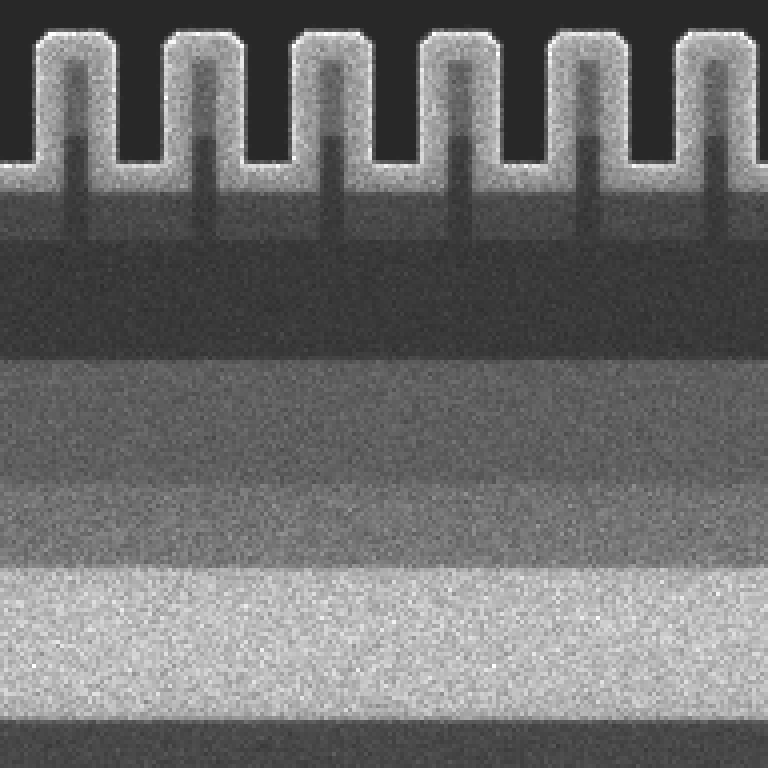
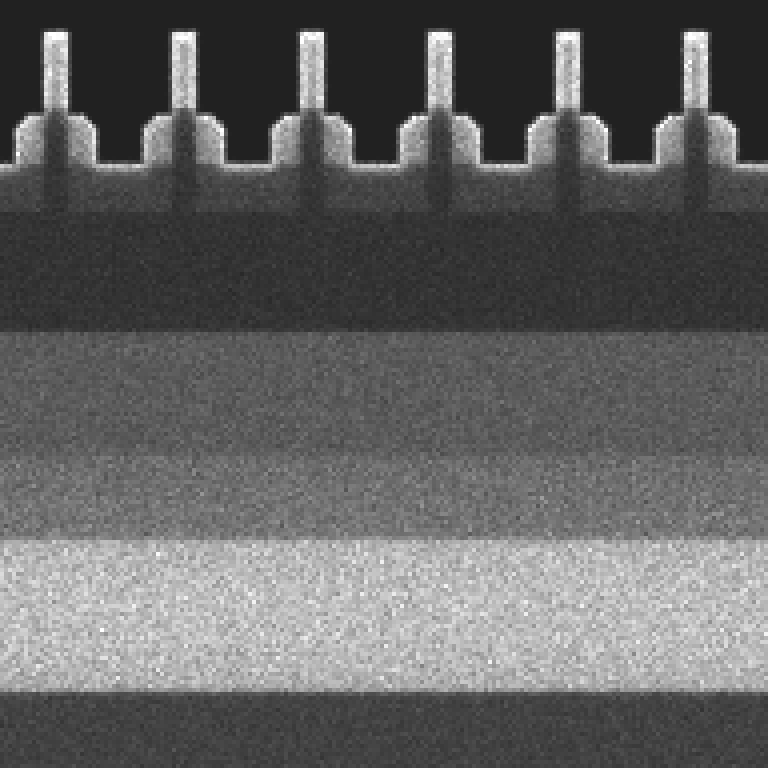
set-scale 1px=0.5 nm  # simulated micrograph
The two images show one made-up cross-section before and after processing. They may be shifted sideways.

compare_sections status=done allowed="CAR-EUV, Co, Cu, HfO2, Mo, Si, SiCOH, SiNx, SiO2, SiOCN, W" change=removed material="W"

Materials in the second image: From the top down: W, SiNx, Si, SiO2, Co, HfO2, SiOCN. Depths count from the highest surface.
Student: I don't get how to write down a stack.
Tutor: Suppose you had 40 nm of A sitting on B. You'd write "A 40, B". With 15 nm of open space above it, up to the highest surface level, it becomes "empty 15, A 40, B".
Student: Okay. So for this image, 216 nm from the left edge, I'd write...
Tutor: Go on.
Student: SiO2 38, Si 112, SiO2 62, Co 42, HfO2 76, SiOCN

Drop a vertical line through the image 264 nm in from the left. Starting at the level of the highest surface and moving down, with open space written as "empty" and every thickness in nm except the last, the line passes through empty 48, W 18, SiNx 24, Si 60, SiO2 62, Co 42, HfO2 76, SiOCN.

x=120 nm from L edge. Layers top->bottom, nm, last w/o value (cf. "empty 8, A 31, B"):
empty 66, SiNx 24, Si 60, SiO2 62, Co 42, HfO2 76, SiOCN